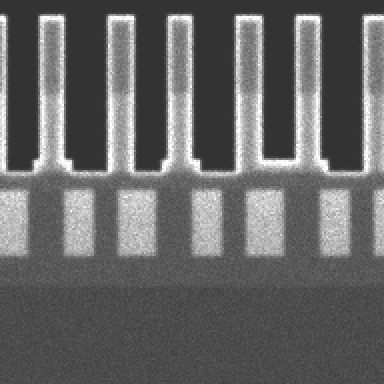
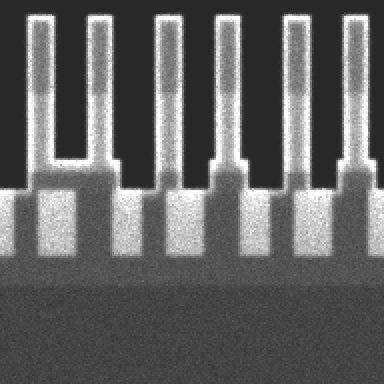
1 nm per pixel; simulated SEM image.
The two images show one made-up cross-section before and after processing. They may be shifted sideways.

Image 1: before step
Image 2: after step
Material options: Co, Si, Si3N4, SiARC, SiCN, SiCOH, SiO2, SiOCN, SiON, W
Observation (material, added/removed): SiCN, removed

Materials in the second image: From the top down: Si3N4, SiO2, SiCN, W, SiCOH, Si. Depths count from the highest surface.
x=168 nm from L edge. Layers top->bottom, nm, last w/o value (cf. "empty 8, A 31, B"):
Si3N4 78, SiO2 78, SiCN 18, W 66, SiCOH 30, Si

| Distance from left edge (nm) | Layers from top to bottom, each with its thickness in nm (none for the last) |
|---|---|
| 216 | Si3N4 78, SiO2 78, SiCN 18, SiCOH 96, Si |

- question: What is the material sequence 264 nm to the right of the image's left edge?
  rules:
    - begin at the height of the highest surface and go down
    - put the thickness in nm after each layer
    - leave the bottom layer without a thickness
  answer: empty 174, W 66, SiCOH 30, Si